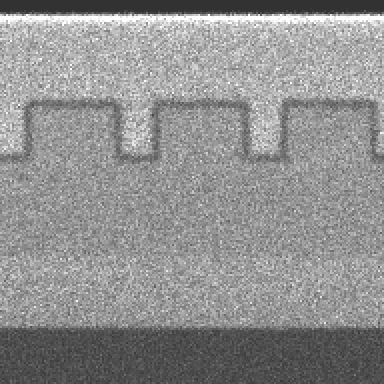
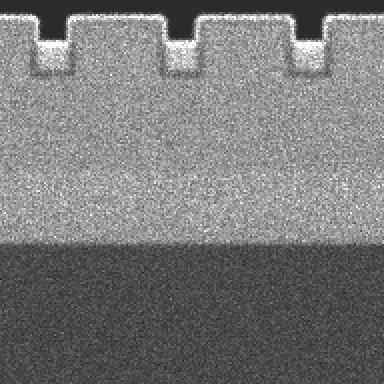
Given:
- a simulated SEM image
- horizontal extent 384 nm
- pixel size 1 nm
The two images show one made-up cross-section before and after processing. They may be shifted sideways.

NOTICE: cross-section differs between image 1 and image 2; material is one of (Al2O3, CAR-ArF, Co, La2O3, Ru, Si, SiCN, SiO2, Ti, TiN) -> removed: Ru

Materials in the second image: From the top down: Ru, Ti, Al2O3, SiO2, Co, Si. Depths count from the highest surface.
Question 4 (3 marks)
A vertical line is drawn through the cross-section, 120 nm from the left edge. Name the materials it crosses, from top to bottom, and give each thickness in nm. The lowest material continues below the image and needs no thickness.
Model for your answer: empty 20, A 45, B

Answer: Ti 8, Al2O3 62, SiO2 86, Co 72, Si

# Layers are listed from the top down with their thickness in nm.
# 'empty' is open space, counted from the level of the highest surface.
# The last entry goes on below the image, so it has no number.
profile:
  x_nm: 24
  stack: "Ti 8, Al2O3 62, SiO2 86, Co 72, Si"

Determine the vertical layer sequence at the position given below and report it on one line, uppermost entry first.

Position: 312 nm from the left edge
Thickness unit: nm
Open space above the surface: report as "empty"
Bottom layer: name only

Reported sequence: empty 26, Ru 28, Ti 8, Al2O3 8, SiO2 86, Co 72, Si